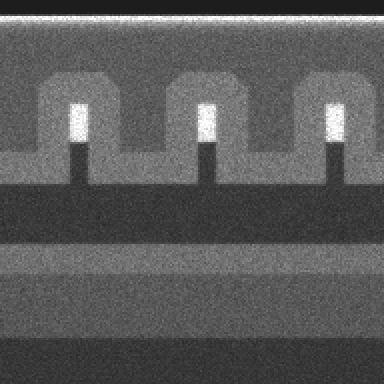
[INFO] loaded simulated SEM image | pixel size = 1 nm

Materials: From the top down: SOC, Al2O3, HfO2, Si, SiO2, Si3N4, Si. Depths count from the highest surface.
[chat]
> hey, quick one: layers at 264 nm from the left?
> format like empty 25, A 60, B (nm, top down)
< SOC 136, Al2O3 32, Si 60, SiO2 30, Si3N4 64, Si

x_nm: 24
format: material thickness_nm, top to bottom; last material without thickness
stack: SOC 136, Al2O3 32, Si 60, SiO2 30, Si3N4 64, Si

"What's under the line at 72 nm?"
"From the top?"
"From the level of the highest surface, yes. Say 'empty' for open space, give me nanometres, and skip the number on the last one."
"SOC 56, Al2O3 32, HfO2 38, Si 102, SiO2 30, Si3N4 64, Si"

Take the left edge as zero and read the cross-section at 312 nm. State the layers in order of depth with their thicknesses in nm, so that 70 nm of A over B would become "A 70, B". SOC 56, Al2O3 112, Si 60, SiO2 30, Si3N4 64, Si